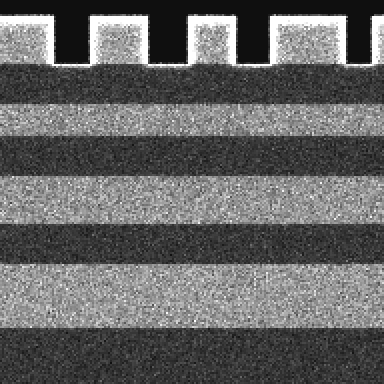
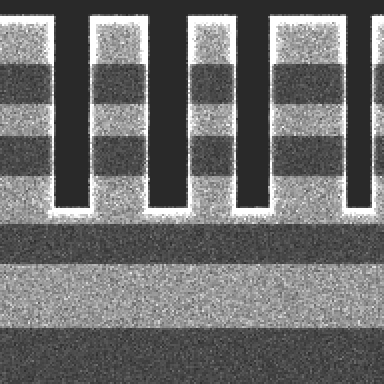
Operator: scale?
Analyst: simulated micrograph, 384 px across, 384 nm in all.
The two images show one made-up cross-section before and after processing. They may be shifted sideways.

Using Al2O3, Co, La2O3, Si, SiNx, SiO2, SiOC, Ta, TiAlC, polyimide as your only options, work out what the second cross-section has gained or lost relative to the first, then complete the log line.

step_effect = removed Co and Si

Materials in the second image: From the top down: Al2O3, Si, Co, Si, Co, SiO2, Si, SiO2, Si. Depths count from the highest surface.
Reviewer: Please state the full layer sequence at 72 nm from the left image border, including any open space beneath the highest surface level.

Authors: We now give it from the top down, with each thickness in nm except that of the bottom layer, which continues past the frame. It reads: empty 192, SiO2 16, Si 40, SiO2 64, Si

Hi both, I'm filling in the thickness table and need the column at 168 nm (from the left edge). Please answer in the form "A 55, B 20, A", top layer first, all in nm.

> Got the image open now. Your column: empty 192, SiO2 16, Si 40, SiO2 64, Si